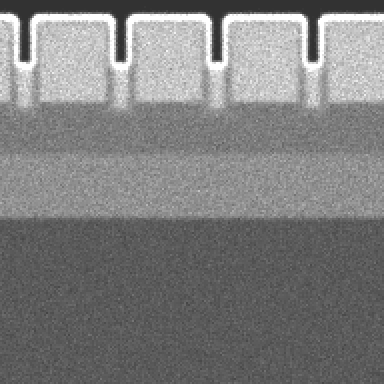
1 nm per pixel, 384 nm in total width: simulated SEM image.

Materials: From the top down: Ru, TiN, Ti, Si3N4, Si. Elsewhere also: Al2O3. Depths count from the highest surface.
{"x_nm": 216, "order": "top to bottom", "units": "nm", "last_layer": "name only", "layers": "empty 48, Ru 44, TiN 8, Ti 38, Si3N4 64, Si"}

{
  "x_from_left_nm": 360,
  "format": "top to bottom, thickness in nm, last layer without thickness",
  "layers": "TiN 8, Al2O3 78, Ti 52, Si3N4 64, Si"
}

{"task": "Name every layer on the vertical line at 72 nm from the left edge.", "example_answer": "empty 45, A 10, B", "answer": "TiN 8, Al2O3 78, Ti 52, Si3N4 64, Si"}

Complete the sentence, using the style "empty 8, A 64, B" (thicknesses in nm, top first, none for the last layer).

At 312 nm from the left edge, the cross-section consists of empty 48, Ru 44, TiN 8, Ti 38, Si3N4 64, Si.